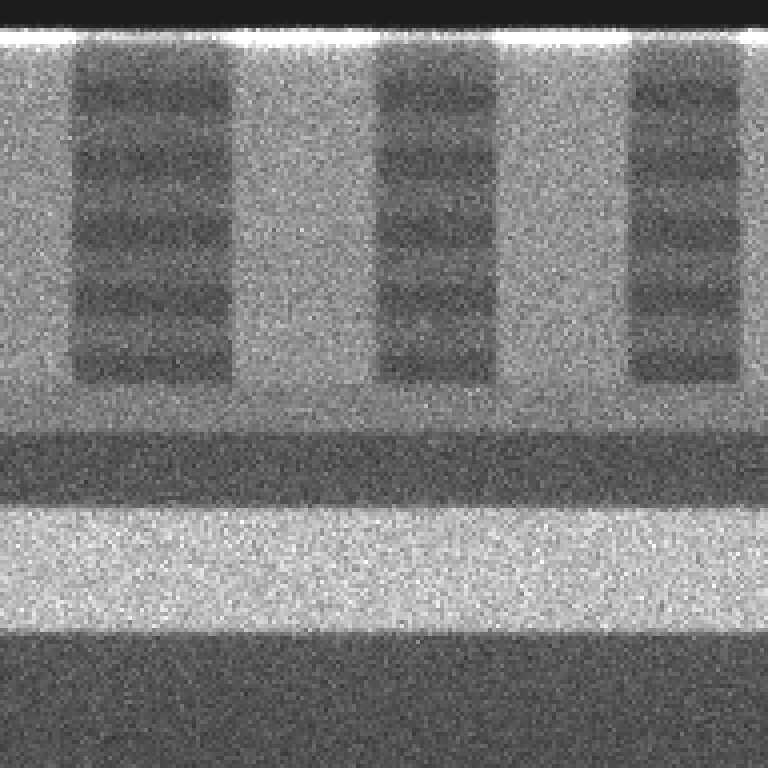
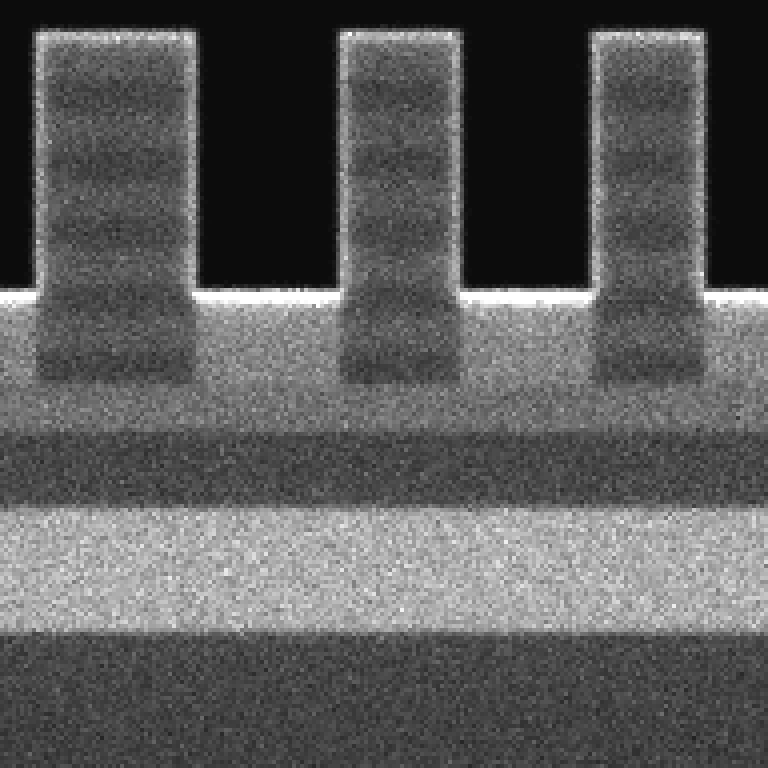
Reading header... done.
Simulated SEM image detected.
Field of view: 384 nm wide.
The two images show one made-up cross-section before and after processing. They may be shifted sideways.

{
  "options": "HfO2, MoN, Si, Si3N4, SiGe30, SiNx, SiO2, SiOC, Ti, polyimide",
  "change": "removed",
  "material": "Si3N4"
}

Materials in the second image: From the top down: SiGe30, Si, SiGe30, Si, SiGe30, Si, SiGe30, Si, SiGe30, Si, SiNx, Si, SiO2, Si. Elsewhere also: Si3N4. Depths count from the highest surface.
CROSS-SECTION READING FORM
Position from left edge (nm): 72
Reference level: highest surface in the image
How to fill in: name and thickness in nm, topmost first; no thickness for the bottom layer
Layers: SiGe30 24, Si 16, SiGe30 18, Si 16, SiGe30 18, Si 16, SiGe30 18, Si 16, SiGe30 18, Si 16, SiNx 24, Si 38, SiO2 62, Si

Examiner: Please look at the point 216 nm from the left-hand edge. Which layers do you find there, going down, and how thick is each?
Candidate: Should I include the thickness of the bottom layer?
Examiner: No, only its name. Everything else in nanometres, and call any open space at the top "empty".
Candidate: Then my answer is SiGe30 24, Si 16, SiGe30 18, Si 16, SiGe30 18, Si 16, SiGe30 18, Si 16, SiGe30 18, Si 16, SiNx 24, Si 38, SiO2 62, Si